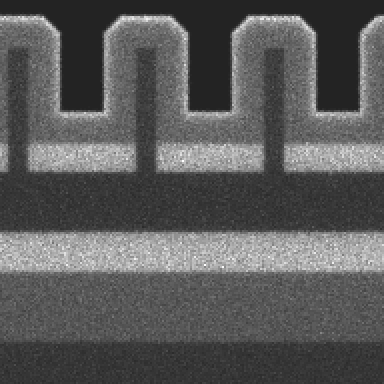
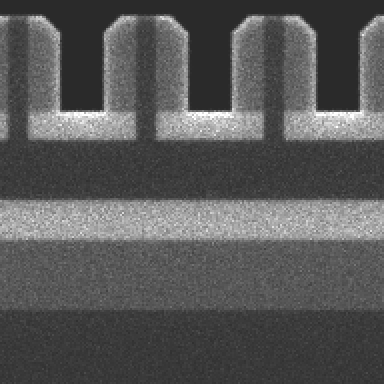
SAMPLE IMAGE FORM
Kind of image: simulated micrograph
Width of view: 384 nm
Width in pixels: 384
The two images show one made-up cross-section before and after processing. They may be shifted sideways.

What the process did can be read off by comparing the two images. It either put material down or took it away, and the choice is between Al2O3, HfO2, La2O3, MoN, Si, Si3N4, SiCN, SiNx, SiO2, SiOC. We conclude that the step removed Al2O3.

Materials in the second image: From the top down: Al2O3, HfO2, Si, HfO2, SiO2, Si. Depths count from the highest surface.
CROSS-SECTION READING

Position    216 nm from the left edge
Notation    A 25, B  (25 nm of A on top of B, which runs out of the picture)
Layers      empty 96, HfO2 28, Si 60, HfO2 40, SiO2 70, Si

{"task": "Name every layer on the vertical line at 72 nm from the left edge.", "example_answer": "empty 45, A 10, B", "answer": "empty 96, HfO2 28, Si 60, HfO2 40, SiO2 70, Si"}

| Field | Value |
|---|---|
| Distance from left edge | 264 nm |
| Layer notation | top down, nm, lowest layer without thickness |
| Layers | Si 184, HfO2 40, SiO2 70, Si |